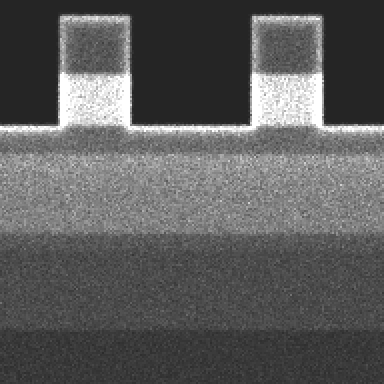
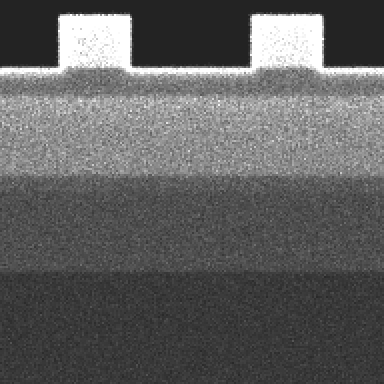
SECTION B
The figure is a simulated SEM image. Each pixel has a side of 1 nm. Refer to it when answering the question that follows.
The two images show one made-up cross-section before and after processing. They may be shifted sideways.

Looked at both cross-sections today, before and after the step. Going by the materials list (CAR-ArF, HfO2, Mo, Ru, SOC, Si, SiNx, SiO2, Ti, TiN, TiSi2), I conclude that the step removed SOC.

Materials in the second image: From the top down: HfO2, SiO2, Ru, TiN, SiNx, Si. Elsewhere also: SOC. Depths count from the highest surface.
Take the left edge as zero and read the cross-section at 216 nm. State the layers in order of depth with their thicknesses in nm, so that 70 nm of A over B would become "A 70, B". empty 52, SiO2 28, Ru 80, TiN 16, SiNx 80, Si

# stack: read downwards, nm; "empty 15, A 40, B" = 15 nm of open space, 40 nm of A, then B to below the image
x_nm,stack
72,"HfO2 52, SiO2 28, Ru 80, TiN 16, SiNx 80, Si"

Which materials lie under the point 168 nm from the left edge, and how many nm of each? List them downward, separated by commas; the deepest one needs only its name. empty 52, SiO2 28, Ru 80, TiN 16, SiNx 80, Si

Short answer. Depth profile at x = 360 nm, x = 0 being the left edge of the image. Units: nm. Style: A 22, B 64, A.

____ empty 52, SiO2 28, Ru 80, TiN 16, SiNx 80, Si